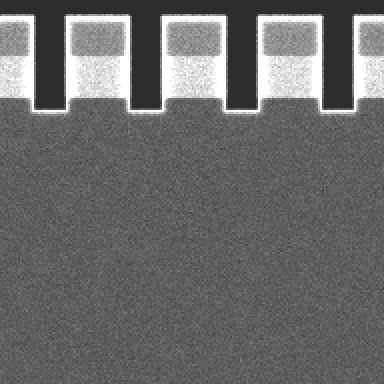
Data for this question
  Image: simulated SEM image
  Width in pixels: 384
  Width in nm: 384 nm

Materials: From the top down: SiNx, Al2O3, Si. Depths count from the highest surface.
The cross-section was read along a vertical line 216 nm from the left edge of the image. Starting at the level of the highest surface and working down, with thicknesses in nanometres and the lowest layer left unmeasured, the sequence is SiNx 40, Al2O3 42, Si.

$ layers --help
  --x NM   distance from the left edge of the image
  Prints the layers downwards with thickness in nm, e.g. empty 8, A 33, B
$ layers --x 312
SiNx 40, Al2O3 42, Si